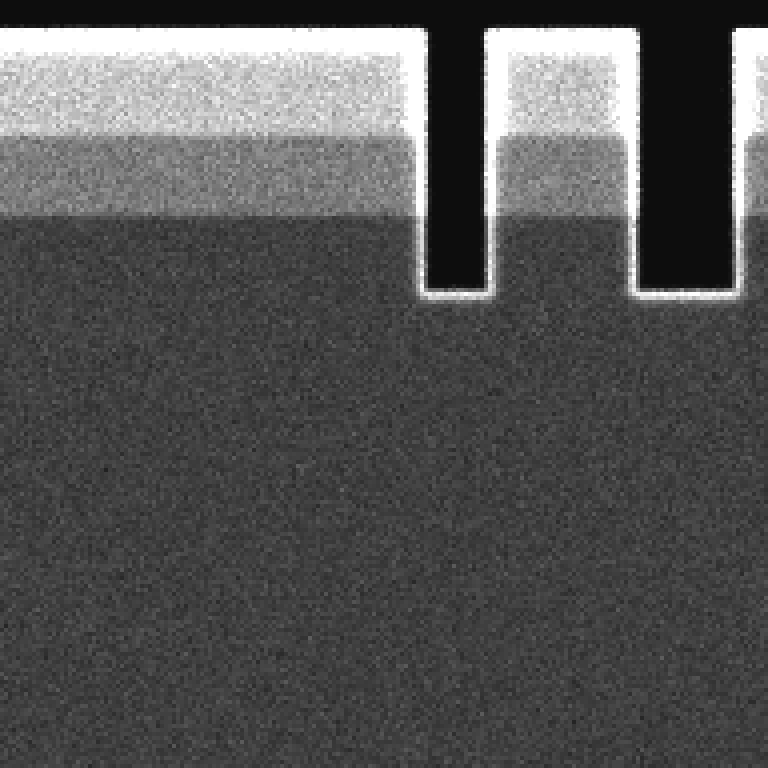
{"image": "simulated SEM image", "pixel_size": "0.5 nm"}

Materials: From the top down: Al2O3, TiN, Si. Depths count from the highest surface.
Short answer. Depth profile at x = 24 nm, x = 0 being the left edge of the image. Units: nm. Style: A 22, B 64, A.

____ Al2O3 52, TiN 40, Si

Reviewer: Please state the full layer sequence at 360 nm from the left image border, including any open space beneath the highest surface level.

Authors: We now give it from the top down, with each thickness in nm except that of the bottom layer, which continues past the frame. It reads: empty 130, Si